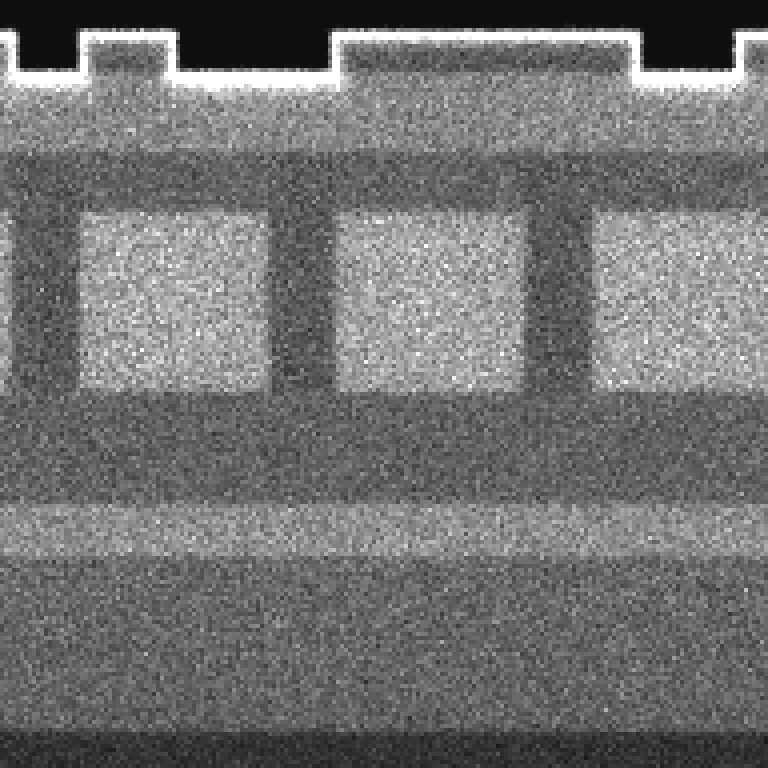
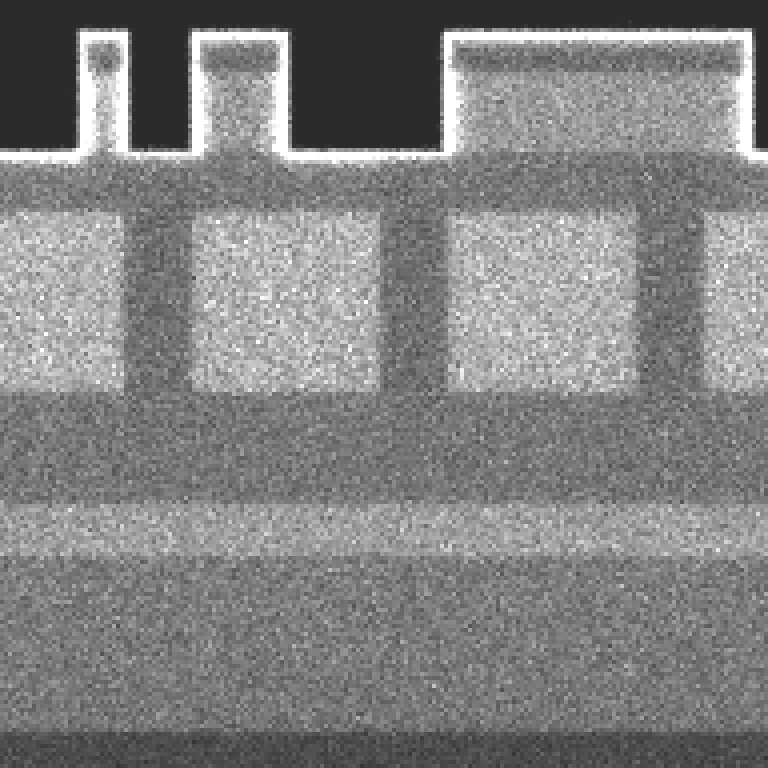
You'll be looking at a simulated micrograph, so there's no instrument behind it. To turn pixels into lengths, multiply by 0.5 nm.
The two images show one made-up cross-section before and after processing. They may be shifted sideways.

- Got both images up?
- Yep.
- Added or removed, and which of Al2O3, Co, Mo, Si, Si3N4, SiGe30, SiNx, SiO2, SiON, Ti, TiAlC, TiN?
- removed, SiO2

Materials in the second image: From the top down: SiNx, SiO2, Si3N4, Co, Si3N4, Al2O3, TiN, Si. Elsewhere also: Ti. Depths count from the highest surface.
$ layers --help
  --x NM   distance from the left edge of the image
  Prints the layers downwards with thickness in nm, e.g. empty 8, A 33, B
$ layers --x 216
empty 60, Ti 120, Si3N4 56, Al2O3 26, TiN 88, Si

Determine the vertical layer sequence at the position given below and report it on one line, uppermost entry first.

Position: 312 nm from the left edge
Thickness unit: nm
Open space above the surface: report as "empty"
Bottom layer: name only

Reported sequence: SiNx 20, SiO2 40, Si3N4 30, Co 90, Si3N4 56, Al2O3 26, TiN 88, Si